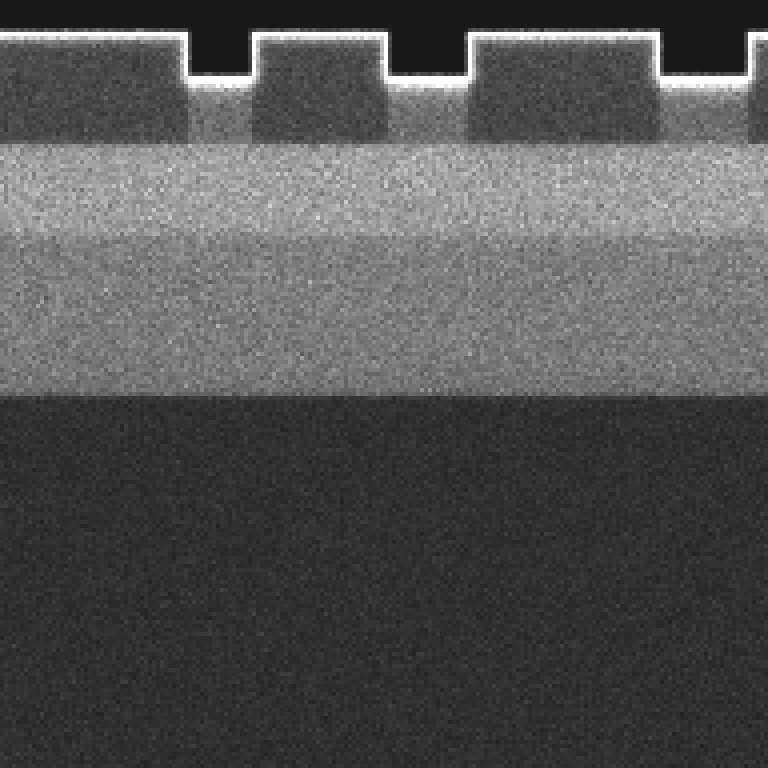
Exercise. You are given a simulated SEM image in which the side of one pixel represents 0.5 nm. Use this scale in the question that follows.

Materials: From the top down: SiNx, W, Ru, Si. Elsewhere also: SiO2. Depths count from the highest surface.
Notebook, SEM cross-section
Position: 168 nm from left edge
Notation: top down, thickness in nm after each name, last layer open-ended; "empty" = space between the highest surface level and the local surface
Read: SiNx 56, W 46, Ru 80, Si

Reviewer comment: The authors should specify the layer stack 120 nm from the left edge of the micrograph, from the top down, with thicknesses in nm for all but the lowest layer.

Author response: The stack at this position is empty 22, SiO2 34, W 46, Ru 80, Si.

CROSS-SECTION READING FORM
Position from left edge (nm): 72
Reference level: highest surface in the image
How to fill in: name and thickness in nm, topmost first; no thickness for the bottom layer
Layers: SiNx 56, W 46, Ru 80, Si